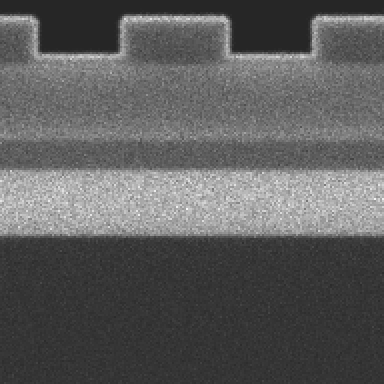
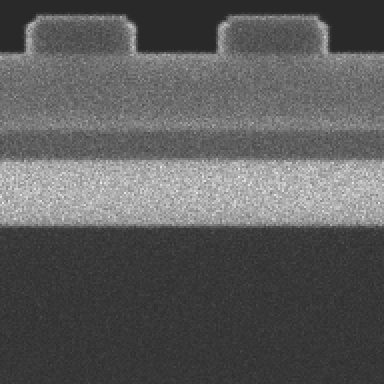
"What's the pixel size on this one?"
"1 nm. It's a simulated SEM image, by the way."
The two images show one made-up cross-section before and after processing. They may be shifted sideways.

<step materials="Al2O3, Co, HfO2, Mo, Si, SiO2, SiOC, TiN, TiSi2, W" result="removed SiO2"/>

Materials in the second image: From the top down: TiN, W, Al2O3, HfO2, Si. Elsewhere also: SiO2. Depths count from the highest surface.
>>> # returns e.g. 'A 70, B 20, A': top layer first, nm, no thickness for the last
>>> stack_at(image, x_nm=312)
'TiN 38, W 76, Al2O3 30, HfO2 66, Si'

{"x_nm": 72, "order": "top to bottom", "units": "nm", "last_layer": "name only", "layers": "TiN 38, W 76, Al2O3 30, HfO2 66, Si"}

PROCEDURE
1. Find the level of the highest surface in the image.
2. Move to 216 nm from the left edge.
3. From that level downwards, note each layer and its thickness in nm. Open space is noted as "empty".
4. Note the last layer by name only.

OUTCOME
empty 38, W 76, Al2O3 30, HfO2 66, Si